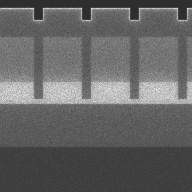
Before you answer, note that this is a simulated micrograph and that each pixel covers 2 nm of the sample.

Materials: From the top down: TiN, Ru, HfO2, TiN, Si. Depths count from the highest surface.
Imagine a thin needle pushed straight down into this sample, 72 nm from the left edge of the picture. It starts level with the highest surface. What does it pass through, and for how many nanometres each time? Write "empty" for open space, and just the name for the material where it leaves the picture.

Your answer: empty 24, TiN 158, HfO2 10, TiN 86, Si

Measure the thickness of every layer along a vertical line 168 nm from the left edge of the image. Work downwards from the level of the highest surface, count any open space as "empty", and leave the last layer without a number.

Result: empty 24, TiN 158, HfO2 10, TiN 86, Si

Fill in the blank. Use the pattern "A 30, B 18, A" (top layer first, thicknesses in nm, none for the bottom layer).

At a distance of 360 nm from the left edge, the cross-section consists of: empty 24, TiN 158, HfO2 10, TiN 86, Si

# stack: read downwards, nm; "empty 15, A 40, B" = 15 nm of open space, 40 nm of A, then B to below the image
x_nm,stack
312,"TiN 58, Ru 90, HfO2 44, TiN 86, Si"